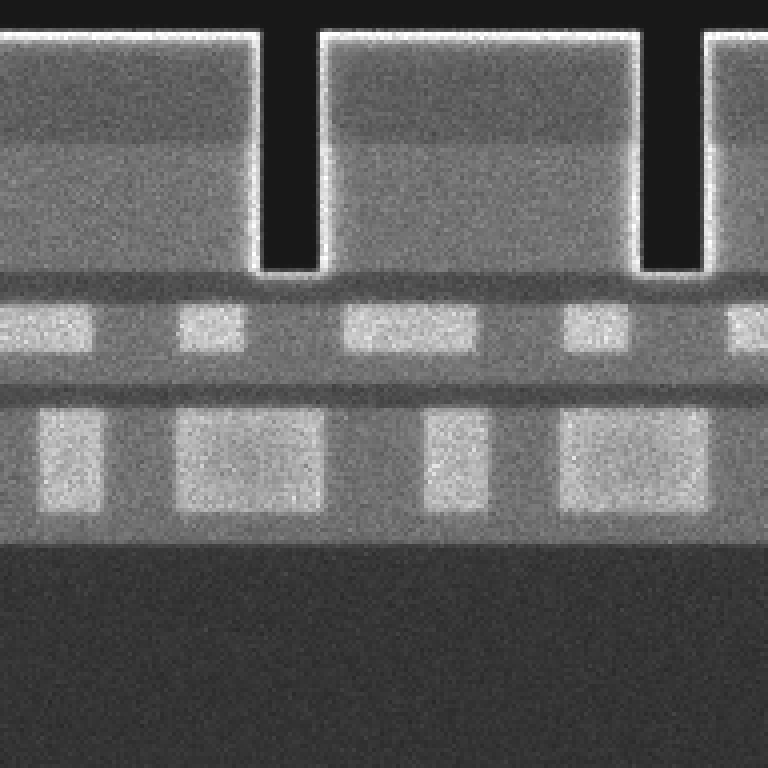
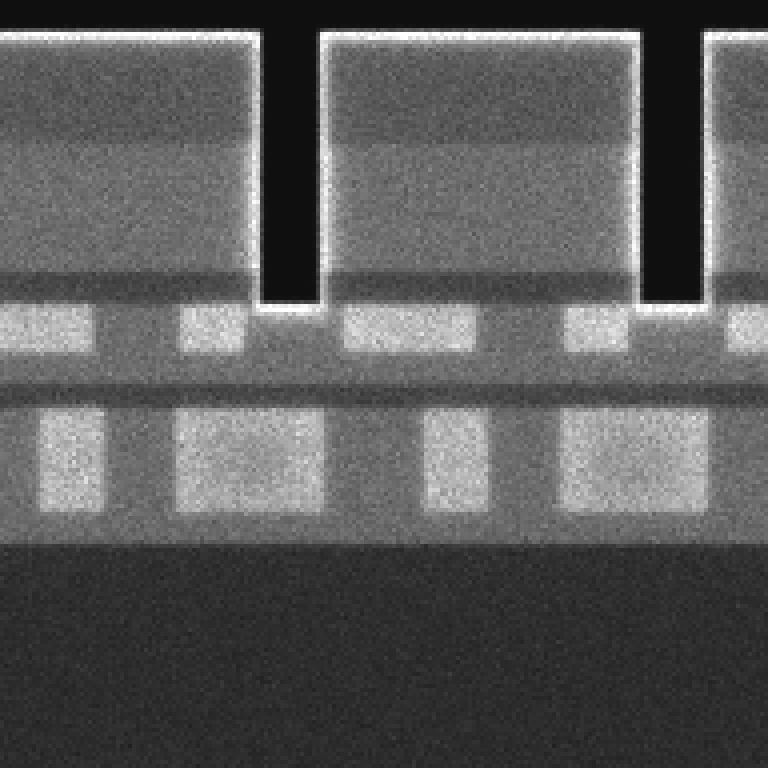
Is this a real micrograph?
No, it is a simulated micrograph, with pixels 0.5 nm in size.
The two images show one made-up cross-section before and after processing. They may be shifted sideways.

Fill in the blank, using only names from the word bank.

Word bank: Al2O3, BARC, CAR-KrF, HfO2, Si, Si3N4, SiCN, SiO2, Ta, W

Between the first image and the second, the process removed SiCN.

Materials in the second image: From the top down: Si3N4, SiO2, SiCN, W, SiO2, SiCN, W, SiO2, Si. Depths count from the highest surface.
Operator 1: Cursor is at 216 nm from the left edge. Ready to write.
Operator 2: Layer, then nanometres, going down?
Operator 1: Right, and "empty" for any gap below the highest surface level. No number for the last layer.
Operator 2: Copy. Si3N4 56, SiO2 64, SiCN 16, W 24, SiO2 16, SiCN 12, W 52, SiO2 16, Si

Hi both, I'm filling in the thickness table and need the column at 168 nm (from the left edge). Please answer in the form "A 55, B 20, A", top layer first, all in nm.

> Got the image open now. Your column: Si3N4 56, SiO2 64, SiCN 16, SiO2 40, SiCN 12, SiO2 68, Si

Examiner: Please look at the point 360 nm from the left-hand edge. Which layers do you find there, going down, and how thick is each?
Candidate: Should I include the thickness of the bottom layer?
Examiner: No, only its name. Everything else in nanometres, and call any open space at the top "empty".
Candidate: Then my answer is Si3N4 56, SiO2 64, SiCN 16, SiO2 40, SiCN 12, SiO2 68, Si